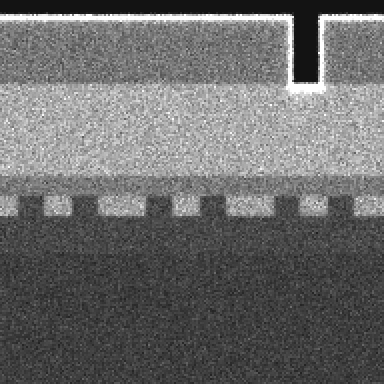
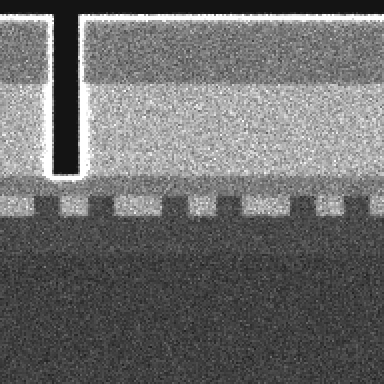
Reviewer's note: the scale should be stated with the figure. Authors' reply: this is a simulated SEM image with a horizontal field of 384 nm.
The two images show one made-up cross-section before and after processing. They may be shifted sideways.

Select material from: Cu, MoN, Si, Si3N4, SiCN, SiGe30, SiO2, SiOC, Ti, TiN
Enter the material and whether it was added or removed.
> SiO2 / removed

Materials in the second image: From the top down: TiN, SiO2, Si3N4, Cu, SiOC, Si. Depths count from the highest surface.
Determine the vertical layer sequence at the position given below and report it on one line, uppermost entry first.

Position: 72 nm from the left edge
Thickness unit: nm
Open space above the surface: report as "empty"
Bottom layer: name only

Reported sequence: empty 160, Si3N4 20, Cu 20, SiOC 38, Si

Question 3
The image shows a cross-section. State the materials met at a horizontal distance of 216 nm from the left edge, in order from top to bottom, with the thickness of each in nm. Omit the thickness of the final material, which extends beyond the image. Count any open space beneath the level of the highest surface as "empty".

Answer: TiN 68, SiO2 92, Si3N4 20, SiOC 58, Si